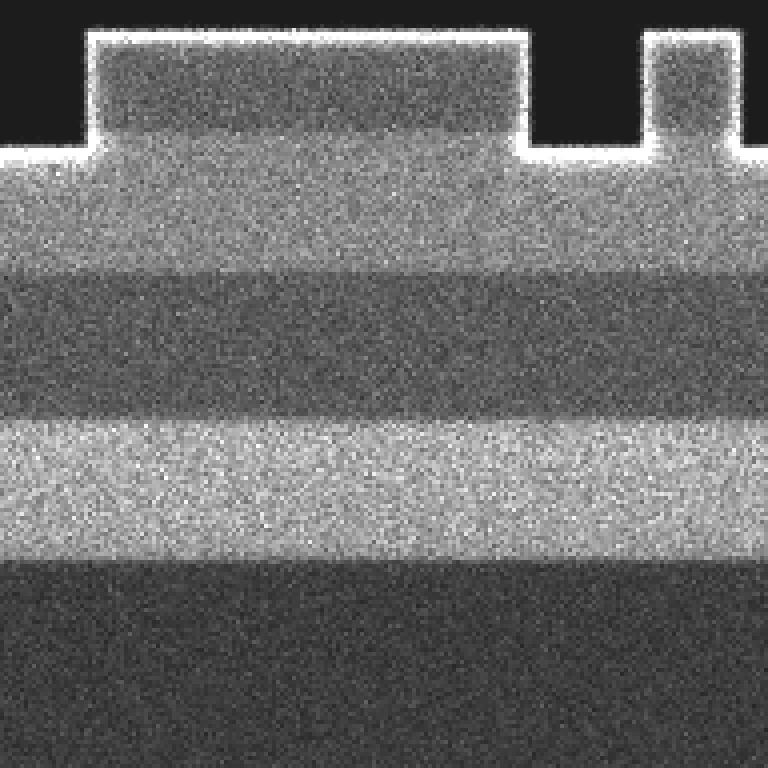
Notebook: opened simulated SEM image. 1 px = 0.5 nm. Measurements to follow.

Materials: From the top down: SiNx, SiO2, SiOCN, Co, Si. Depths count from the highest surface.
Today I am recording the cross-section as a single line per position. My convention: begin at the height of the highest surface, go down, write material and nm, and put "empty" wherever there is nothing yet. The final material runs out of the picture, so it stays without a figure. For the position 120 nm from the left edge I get SiNx 50, SiO2 70, SiOCN 74, Co 70, Si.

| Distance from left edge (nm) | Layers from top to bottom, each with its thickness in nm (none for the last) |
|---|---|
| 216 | SiNx 50, SiO2 70, SiOCN 74, Co 70, Si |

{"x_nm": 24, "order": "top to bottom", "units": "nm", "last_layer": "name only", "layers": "empty 58, SiO2 62, SiOCN 74, Co 70, Si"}